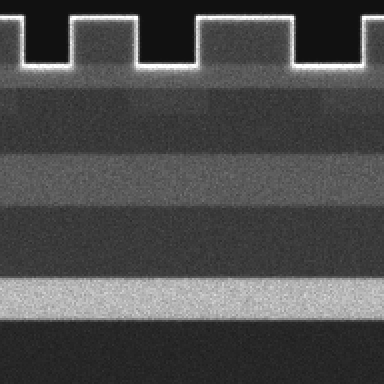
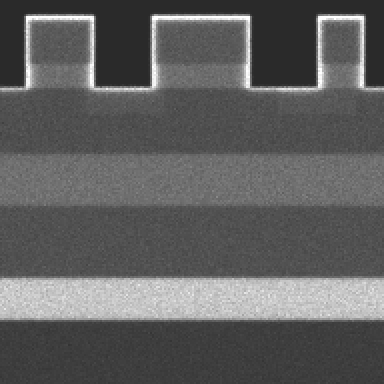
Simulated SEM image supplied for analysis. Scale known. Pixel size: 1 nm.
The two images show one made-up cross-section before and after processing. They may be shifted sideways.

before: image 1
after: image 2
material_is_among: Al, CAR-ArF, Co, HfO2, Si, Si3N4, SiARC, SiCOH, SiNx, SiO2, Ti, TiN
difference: SiO2, removed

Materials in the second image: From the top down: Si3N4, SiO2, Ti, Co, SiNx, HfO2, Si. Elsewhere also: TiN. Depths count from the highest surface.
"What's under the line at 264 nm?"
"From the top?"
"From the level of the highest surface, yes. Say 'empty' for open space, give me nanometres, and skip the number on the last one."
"empty 72, Ti 66, Co 52, SiNx 72, HfO2 42, Si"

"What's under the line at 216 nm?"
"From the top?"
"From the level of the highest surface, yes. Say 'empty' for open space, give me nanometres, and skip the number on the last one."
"Si3N4 48, SiO2 24, Ti 66, Co 52, SiNx 72, HfO2 42, Si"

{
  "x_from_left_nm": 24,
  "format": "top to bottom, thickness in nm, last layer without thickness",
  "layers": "empty 72, Ti 66, Co 52, SiNx 72, HfO2 42, Si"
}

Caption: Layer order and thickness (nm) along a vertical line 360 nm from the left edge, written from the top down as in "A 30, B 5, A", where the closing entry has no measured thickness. Si3N4 48, SiO2 24, Ti 66, Co 52, SiNx 72, HfO2 42, Si